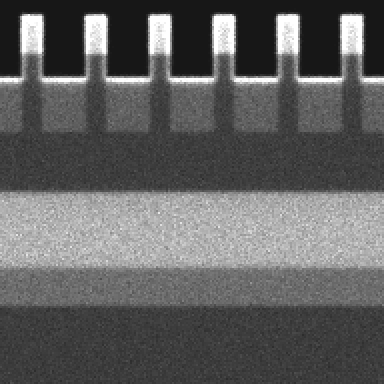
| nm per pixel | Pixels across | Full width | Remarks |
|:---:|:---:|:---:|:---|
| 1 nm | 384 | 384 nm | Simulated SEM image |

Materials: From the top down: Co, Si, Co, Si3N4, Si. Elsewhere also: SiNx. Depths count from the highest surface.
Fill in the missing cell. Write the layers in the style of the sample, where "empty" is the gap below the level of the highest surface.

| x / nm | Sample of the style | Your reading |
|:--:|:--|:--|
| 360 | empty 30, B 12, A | Co 38, Si 138, Co 76, Si3N4 38, Si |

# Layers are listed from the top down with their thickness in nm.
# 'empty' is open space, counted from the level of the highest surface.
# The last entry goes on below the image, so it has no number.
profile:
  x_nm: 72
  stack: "empty 62, SiNx 54, Si 60, Co 76, Si3N4 38, Si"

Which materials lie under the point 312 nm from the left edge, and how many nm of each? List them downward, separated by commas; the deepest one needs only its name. empty 62, SiNx 54, Si 60, Co 76, Si3N4 38, Si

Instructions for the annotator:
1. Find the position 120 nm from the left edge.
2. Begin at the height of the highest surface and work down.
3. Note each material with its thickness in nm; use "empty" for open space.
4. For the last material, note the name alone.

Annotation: empty 62, SiNx 54, Si 60, Co 76, Si3N4 38, Si